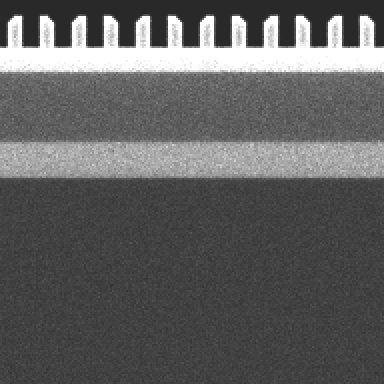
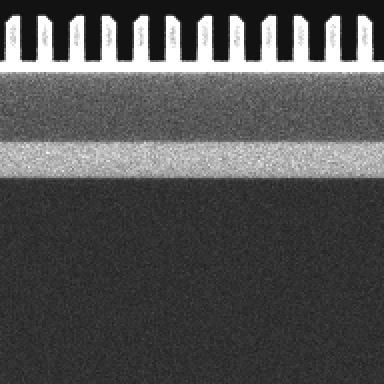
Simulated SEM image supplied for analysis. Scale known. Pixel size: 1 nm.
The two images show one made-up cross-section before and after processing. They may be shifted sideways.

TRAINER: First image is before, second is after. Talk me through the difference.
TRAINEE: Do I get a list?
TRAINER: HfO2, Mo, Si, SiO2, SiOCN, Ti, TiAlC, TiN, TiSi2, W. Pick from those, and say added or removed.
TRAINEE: removed: HfO2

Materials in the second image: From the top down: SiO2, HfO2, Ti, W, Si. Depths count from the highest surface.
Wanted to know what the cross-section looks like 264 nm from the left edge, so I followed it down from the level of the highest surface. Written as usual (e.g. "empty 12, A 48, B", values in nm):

empty 4, SiO2 28, HfO2 24, Ti 70, W 36, Si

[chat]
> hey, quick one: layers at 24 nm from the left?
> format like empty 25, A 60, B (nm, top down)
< empty 46, HfO2 10, Ti 70, W 36, Si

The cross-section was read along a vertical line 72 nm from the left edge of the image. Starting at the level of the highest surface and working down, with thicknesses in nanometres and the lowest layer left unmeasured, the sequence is empty 4, SiO2 28, HfO2 24, Ti 70, W 36, Si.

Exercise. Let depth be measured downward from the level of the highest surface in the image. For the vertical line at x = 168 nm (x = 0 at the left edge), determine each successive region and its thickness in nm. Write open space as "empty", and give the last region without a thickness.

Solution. SiO2 32, HfO2 24, Ti 70, W 36, Si